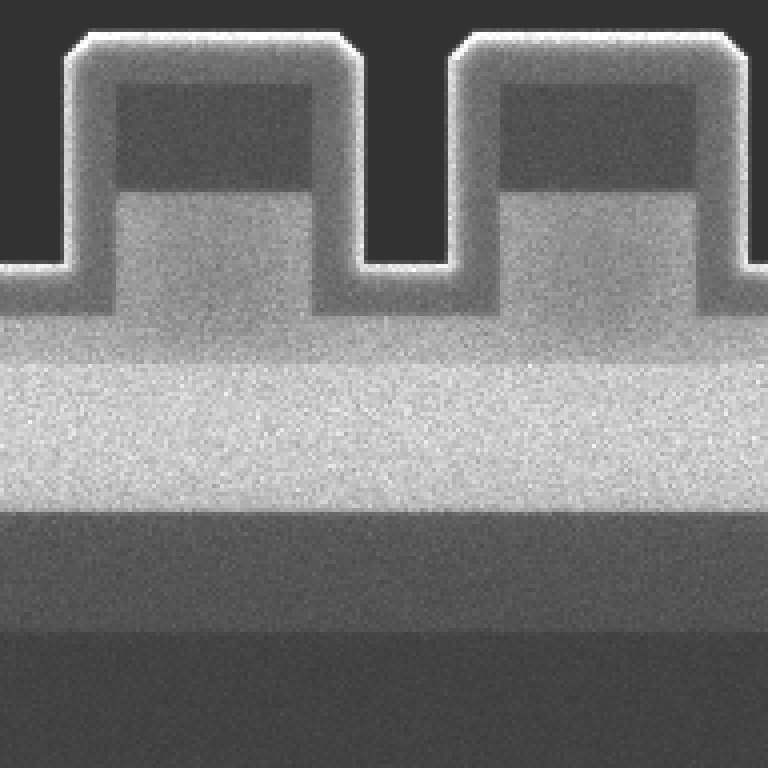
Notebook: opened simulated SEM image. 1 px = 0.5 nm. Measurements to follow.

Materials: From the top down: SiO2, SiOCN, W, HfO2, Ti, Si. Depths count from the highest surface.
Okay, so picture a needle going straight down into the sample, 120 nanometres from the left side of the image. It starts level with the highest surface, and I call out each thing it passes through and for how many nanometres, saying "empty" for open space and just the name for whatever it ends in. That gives SiO2 26, SiOCN 54, W 86, HfO2 74, Ti 60, Si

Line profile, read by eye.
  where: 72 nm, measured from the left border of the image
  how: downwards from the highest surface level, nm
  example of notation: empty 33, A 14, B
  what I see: SiO2 26, SiOCN 54, W 86, HfO2 74, Ti 60, Si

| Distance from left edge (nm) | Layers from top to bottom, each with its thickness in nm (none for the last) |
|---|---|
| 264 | SiO2 26, SiOCN 54, W 86, HfO2 74, Ti 60, Si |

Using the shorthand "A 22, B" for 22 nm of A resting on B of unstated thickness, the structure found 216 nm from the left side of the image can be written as empty 116, SiO2 26, W 24, HfO2 74, Ti 60, Si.